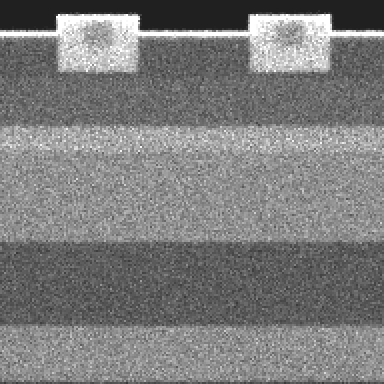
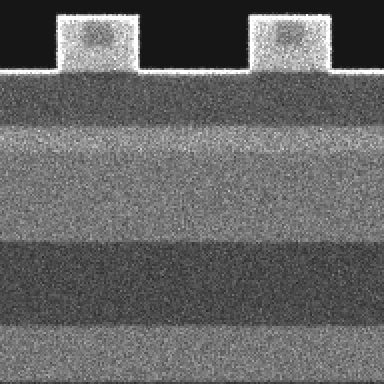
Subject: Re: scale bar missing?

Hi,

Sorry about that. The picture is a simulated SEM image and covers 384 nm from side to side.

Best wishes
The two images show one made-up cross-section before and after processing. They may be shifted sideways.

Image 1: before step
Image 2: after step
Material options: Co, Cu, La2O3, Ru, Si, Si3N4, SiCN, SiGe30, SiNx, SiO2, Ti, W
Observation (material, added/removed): SiNx, removed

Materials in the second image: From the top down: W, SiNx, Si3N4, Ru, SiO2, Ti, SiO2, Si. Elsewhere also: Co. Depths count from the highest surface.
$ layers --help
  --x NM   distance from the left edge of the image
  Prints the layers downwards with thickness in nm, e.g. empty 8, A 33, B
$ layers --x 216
empty 54, SiNx 8, Si3N4 48, Ru 26, SiO2 90, Ti 84, SiO2 56, Si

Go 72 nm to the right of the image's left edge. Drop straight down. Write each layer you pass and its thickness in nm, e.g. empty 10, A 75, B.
W 56, SiNx 6, Si3N4 48, Ru 26, SiO2 90, Ti 84, SiO2 56, Si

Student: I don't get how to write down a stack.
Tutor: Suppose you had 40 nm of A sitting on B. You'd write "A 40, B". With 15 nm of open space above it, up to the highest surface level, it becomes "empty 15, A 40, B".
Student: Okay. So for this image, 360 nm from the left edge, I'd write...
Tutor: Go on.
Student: empty 54, SiNx 8, Si3N4 48, Ru 26, SiO2 90, Ti 84, SiO2 56, Si